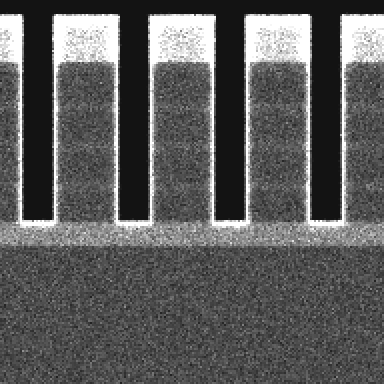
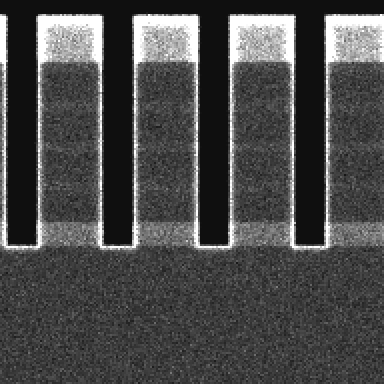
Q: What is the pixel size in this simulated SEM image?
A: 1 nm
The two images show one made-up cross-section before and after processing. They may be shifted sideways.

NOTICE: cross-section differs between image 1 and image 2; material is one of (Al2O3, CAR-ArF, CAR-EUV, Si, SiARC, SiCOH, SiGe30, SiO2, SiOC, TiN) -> removed: TiN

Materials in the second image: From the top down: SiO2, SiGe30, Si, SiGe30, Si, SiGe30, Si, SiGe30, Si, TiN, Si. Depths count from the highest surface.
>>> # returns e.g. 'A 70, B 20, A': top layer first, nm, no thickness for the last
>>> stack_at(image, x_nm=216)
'empty 230, Si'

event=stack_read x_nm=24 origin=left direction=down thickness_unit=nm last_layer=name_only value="empty 230, Si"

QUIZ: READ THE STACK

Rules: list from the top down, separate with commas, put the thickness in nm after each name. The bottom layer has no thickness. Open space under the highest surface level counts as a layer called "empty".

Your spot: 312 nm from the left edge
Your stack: empty 230, Si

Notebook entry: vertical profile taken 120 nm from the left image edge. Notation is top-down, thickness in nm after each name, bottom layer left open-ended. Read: empty 230, Si